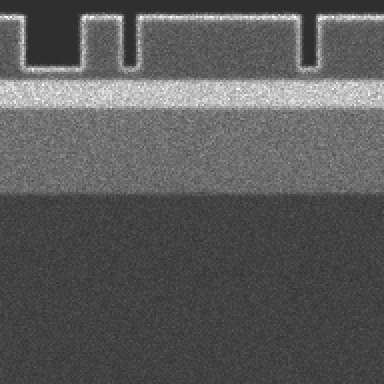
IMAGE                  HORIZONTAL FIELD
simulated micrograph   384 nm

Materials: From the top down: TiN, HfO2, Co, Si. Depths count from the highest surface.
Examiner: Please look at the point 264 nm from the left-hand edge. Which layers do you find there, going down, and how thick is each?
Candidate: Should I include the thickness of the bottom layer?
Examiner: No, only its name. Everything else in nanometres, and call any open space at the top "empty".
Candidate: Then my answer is TiN 64, HfO2 28, Co 86, Si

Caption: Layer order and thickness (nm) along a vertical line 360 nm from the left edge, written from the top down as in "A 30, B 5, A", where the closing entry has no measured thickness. TiN 64, HfO2 28, Co 86, Si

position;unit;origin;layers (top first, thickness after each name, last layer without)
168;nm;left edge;TiN 64, HfO2 28, Co 86, Si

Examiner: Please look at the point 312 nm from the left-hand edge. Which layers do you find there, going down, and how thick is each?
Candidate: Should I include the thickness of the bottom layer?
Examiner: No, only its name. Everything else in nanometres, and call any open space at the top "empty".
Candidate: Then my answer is empty 52, TiN 12, HfO2 28, Co 86, Si